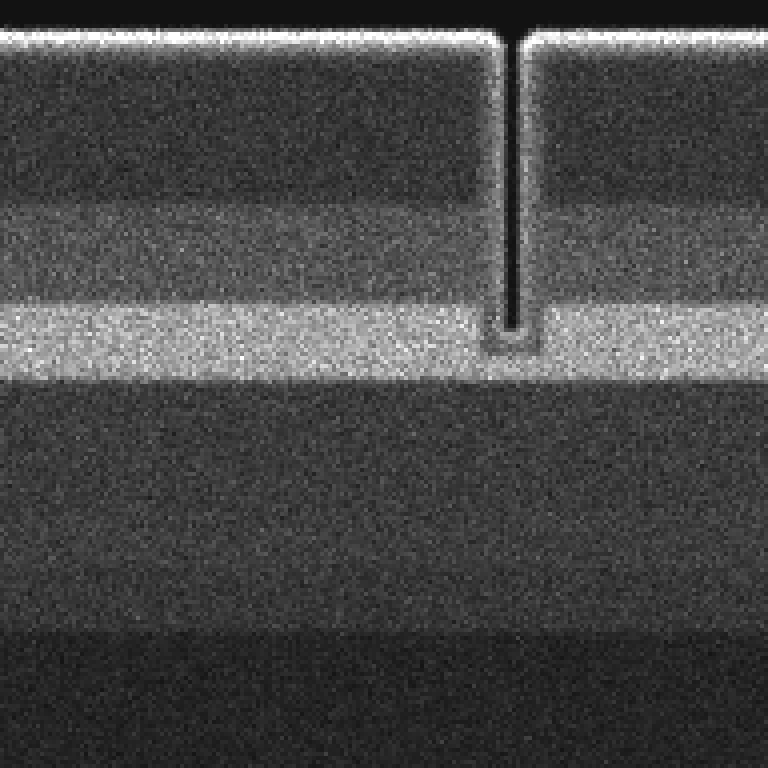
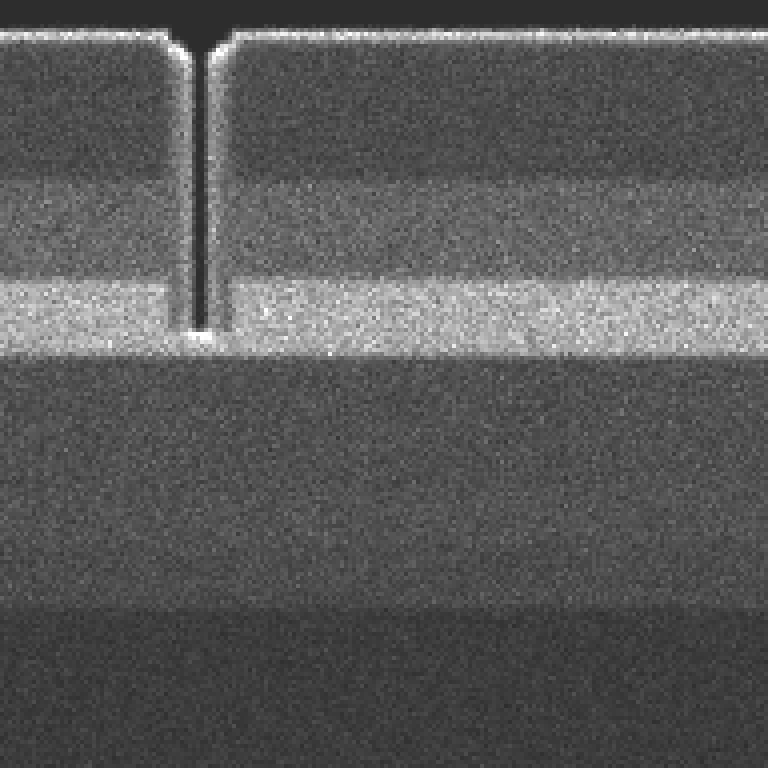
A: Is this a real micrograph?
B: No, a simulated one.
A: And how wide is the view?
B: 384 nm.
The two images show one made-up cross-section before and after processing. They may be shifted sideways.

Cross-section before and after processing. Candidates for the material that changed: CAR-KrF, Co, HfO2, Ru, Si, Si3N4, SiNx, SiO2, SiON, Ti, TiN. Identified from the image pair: SiO2 (removed).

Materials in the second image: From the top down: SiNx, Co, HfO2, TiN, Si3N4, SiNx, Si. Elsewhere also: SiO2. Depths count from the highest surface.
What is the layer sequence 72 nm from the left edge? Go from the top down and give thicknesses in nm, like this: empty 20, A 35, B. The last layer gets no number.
SiNx 74, Co 50, HfO2 38, TiN 66, Si3N4 28, SiNx 32, Si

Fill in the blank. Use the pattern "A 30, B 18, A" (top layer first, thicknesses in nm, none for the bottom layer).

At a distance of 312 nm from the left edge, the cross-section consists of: SiNx 74, Co 50, HfO2 38, TiN 66, Si3N4 28, SiNx 32, Si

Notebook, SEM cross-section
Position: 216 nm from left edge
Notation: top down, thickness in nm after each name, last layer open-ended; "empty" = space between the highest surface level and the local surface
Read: SiNx 74, Co 50, HfO2 38, TiN 66, Si3N4 28, SiNx 32, Si